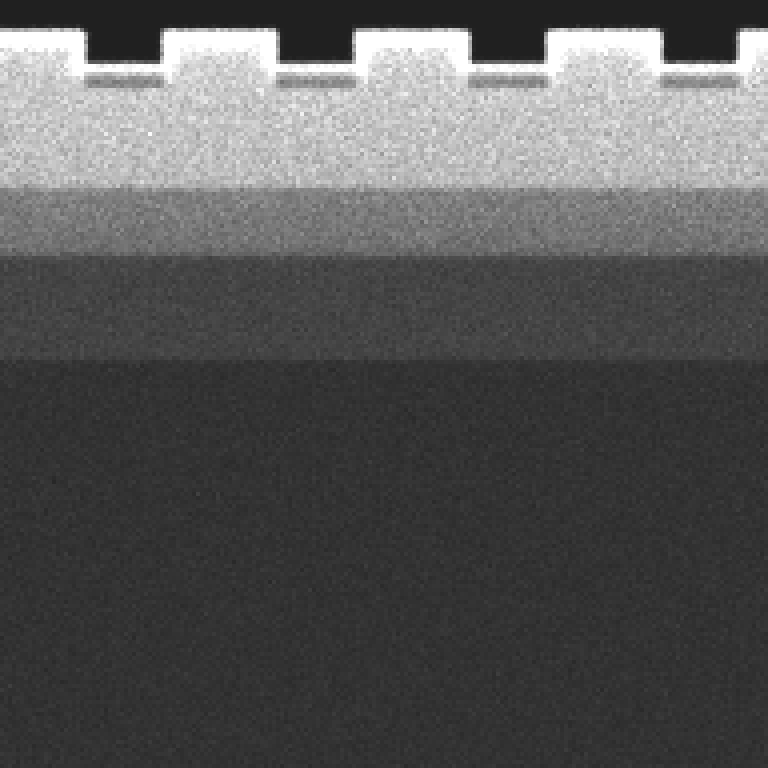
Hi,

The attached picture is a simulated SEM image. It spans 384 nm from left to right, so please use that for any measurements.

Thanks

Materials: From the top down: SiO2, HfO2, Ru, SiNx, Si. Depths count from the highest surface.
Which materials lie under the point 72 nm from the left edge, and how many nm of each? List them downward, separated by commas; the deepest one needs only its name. empty 16, SiO2 12, HfO2 50, Ru 34, SiNx 52, Si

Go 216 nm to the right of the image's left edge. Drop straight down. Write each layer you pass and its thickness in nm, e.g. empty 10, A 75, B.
HfO2 78, Ru 34, SiNx 52, Si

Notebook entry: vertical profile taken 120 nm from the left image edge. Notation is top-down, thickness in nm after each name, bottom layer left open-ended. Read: HfO2 78, Ru 34, SiNx 52, Si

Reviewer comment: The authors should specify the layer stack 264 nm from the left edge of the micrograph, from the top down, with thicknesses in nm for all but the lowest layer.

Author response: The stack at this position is empty 16, SiO2 12, HfO2 50, Ru 34, SiNx 52, Si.